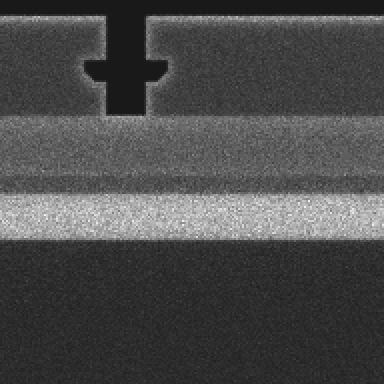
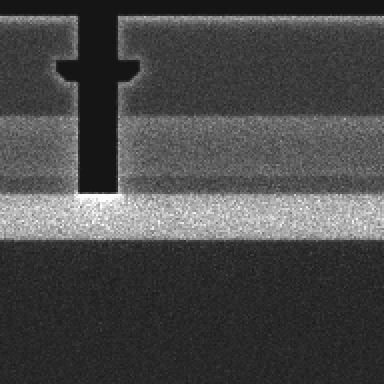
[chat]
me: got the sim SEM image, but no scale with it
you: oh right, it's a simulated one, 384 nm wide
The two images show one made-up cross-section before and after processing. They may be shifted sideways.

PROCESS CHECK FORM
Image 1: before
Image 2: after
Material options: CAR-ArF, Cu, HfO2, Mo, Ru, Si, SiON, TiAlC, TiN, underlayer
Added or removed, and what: removed, Ru and TiN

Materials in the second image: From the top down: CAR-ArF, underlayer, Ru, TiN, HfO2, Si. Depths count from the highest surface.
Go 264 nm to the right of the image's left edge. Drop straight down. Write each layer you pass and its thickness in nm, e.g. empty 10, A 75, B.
CAR-ArF 44, underlayer 56, Ru 60, TiN 18, HfO2 46, Si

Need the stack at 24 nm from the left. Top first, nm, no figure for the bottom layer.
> CAR-ArF 44, underlayer 56, Ru 60, TiN 18, HfO2 46, Si